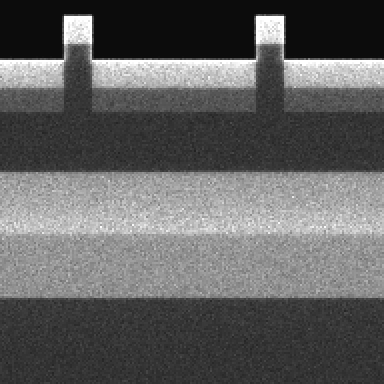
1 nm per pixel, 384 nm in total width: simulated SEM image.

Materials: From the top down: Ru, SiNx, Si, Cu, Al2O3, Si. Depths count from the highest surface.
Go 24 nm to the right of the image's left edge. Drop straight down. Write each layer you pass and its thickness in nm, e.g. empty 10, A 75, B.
empty 44, Ru 28, SiNx 24, Si 60, Cu 62, Al2O3 64, Si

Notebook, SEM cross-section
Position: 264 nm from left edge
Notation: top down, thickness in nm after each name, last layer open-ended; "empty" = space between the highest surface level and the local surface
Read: Ru 28, Si 128, Cu 62, Al2O3 64, Si